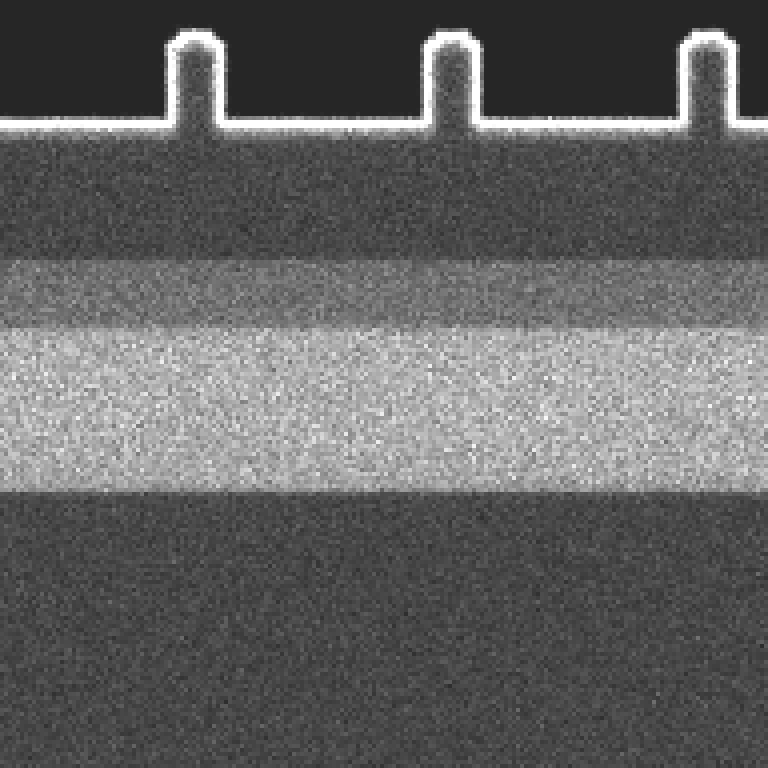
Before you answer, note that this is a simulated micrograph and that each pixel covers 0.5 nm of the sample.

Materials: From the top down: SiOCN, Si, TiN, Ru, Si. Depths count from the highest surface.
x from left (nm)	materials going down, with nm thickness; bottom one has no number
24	empty 44, SiOCN 10, Si 60, TiN 34, Ru 82, Si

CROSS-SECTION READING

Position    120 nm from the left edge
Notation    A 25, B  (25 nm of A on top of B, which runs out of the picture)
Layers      empty 44, SiOCN 10, Si 60, TiN 34, Ru 82, Si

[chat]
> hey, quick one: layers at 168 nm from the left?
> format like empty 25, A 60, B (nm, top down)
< empty 44, SiOCN 10, Si 60, TiN 34, Ru 82, Si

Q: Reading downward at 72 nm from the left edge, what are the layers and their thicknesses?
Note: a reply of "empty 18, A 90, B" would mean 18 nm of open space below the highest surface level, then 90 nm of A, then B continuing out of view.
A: empty 44, SiOCN 10, Si 60, TiN 34, Ru 82, Si